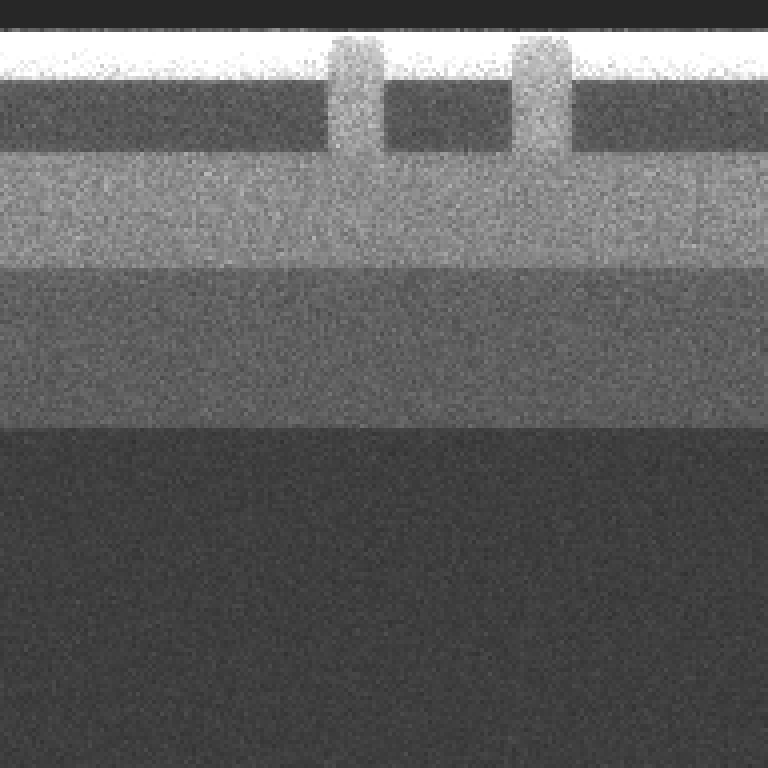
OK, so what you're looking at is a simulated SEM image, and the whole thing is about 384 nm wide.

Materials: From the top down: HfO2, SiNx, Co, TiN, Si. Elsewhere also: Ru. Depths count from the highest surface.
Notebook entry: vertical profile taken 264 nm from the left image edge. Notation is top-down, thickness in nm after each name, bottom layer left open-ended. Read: Ru 60, Co 58, TiN 80, Si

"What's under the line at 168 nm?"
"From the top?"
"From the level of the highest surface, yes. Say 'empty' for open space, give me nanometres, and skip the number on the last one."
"Ru 60, Co 58, TiN 80, Si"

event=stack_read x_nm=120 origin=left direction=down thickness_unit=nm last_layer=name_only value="HfO2 24, SiNx 36, Co 58, TiN 80, Si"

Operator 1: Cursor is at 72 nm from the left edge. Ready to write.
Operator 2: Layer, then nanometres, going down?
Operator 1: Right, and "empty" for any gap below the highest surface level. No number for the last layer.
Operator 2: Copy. HfO2 24, SiNx 36, Co 58, TiN 80, Si